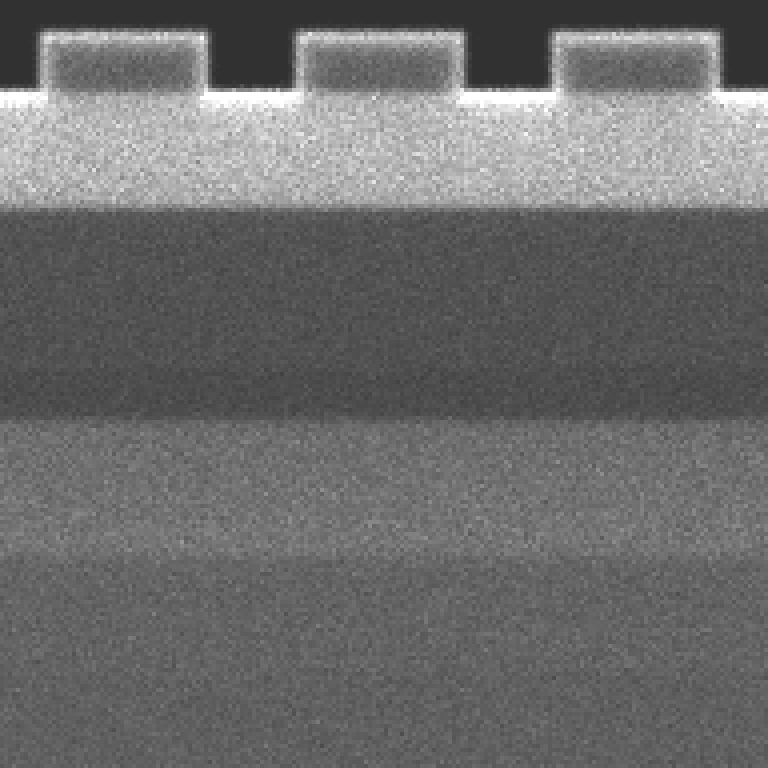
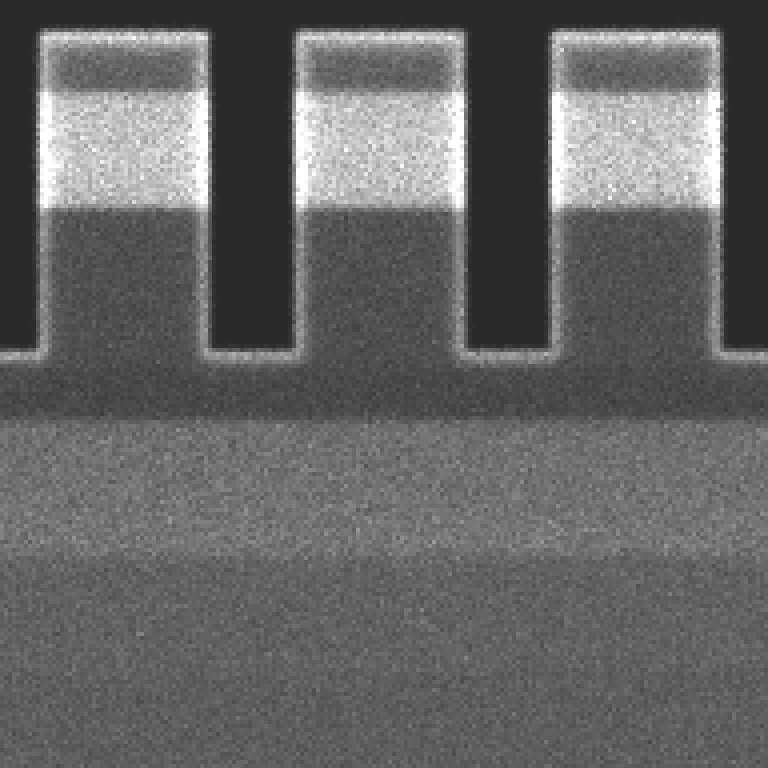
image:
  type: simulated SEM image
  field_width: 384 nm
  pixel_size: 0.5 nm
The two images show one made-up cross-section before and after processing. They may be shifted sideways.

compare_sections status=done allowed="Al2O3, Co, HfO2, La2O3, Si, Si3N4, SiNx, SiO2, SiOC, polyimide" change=removed material="HfO2 and Si3N4"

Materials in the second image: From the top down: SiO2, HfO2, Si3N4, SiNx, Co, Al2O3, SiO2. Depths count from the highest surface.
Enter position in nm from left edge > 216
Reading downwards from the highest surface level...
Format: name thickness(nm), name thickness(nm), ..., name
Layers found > SiO2 30, HfO2 58, Si3N4 80, SiNx 26, Co 68, Al2O3 58, SiO2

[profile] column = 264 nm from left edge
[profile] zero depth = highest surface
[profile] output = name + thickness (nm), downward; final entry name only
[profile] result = empty 160, Si3N4 8, SiNx 26, Co 68, Al2O3 58, SiO2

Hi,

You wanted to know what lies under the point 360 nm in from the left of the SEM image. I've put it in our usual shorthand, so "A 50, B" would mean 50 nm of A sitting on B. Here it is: empty 160, Si3N4 8, SiNx 26, Co 68, Al2O3 58, SiO2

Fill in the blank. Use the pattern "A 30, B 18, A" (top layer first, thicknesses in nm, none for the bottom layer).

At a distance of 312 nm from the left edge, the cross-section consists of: SiO2 30, HfO2 58, Si3N4 80, SiNx 26, Co 68, Al2O3 58, SiO2